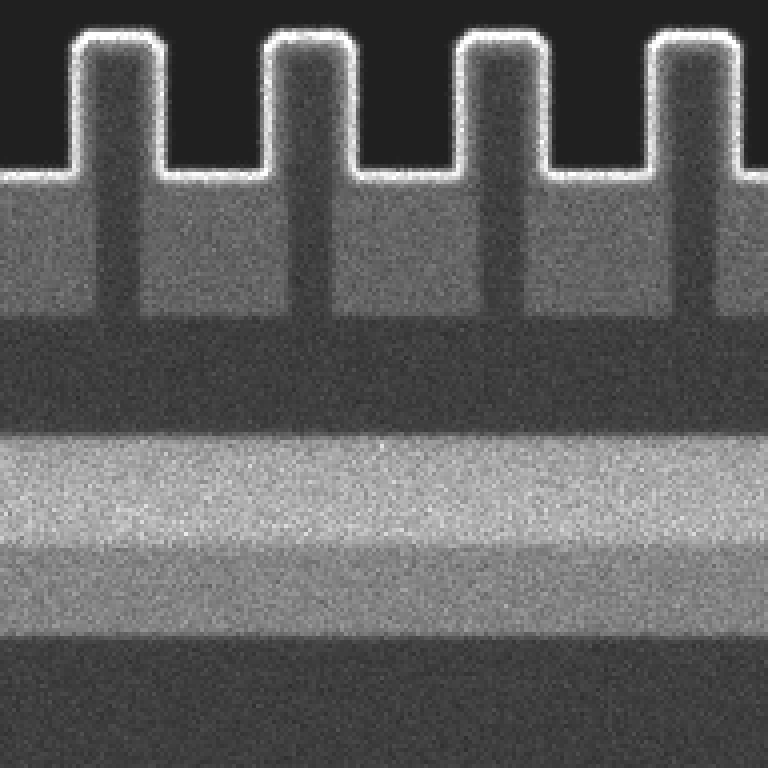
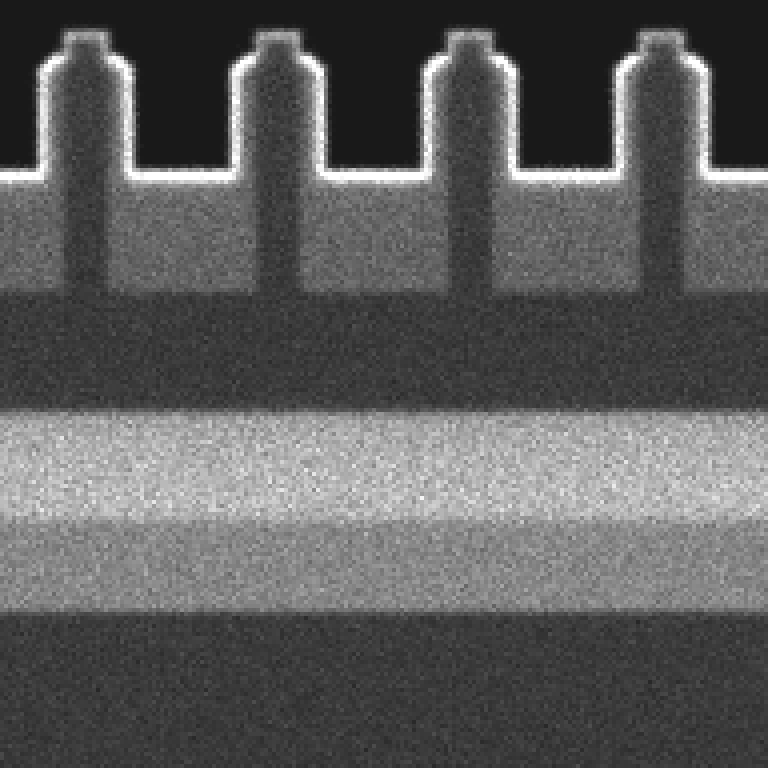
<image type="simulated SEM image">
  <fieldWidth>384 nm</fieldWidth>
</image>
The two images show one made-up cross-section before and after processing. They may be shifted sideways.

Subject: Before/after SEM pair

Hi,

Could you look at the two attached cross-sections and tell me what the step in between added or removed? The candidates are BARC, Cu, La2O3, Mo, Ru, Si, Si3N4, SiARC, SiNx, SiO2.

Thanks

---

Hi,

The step removed SiNx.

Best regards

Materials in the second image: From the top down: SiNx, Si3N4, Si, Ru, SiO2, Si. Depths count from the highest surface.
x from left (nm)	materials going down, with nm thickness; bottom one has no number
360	empty 70, Si3N4 60, Si 60, Ru 54, SiO2 46, Si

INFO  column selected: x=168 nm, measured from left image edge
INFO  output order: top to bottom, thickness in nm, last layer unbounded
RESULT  empty 70, Si3N4 60, Si 60, Ru 54, SiO2 46, Si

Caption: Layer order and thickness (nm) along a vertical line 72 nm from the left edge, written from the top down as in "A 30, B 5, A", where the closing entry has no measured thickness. empty 70, Si3N4 60, Si 60, Ru 54, SiO2 46, Si